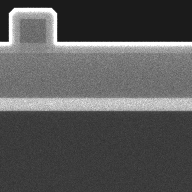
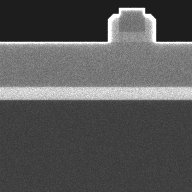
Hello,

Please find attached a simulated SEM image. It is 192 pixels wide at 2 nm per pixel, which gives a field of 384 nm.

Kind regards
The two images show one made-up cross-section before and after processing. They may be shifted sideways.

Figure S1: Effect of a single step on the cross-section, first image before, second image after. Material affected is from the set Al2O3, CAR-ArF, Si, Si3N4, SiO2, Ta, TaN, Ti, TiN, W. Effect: removed Al2O3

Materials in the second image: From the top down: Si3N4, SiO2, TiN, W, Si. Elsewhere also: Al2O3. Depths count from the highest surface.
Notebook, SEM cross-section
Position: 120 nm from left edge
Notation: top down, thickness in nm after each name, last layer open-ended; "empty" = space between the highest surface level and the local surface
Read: empty 68, TiN 90, W 26, Si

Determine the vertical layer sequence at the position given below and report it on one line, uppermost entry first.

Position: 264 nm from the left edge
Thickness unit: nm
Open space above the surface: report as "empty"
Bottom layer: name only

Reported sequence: Si3N4 48, SiO2 20, TiN 90, W 26, Si